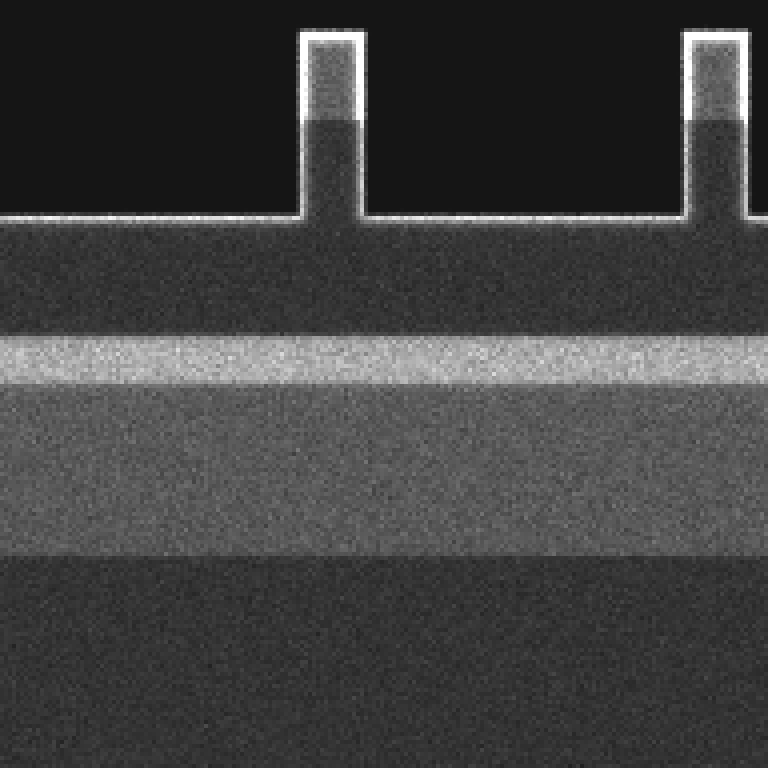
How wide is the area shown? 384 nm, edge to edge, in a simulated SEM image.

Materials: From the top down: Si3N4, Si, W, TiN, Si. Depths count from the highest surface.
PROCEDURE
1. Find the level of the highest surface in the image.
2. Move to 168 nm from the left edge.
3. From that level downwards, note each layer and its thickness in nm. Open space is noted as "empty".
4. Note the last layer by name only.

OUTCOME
Si3N4 44, Si 108, W 24, TiN 86, Si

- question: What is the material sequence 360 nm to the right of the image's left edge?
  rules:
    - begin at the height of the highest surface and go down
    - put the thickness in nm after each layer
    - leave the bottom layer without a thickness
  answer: Si3N4 44, Si 108, W 24, TiN 86, Si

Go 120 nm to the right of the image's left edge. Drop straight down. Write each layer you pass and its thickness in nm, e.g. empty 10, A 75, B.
empty 92, Si 60, W 24, TiN 86, Si